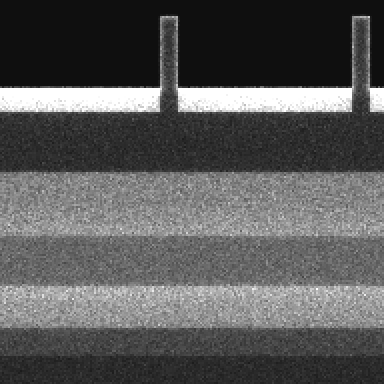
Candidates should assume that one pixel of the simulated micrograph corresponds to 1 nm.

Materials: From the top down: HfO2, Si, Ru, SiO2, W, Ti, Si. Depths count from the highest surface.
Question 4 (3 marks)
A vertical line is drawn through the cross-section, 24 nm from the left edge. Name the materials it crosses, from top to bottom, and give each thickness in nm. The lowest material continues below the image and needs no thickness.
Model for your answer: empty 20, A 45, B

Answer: empty 72, HfO2 24, Si 60, Ru 64, SiO2 50, W 42, Ti 28, Si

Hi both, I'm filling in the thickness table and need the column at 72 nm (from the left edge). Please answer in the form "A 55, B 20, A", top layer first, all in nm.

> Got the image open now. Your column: empty 72, HfO2 24, Si 60, Ru 64, SiO2 50, W 42, Ti 28, Si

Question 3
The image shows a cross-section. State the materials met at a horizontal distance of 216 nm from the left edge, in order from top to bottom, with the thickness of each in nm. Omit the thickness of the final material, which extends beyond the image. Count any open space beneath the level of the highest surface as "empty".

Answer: empty 72, HfO2 24, Si 60, Ru 64, SiO2 50, W 42, Ti 28, Si